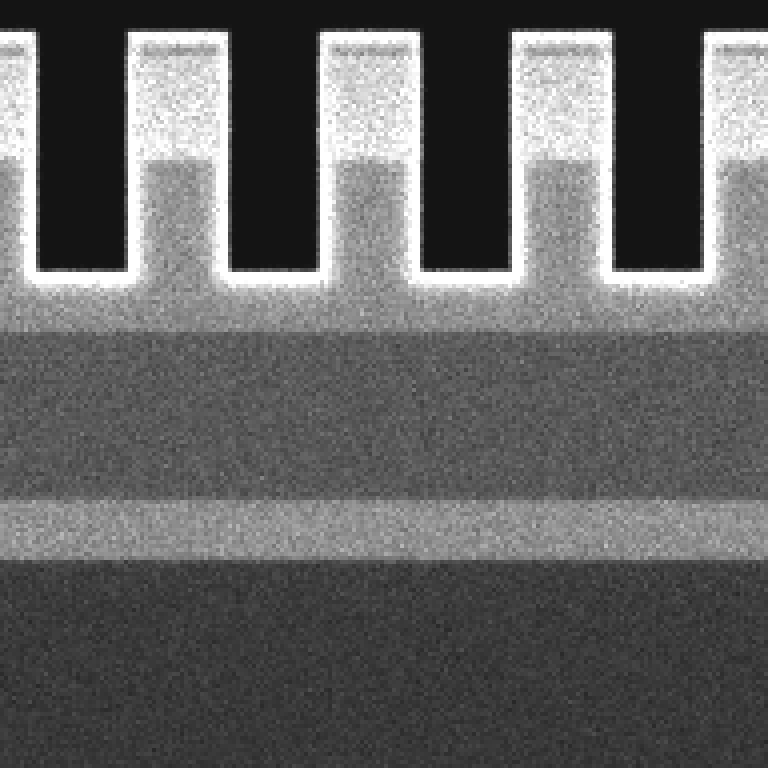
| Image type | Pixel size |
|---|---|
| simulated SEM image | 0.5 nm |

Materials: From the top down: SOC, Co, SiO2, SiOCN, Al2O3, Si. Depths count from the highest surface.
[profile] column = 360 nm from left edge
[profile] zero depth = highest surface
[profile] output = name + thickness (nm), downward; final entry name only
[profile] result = SOC 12, Co 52, SiO2 86, SiOCN 84, Al2O3 30, Si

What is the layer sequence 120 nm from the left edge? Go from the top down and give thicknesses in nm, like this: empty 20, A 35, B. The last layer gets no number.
empty 120, SiO2 30, SiOCN 84, Al2O3 30, Si